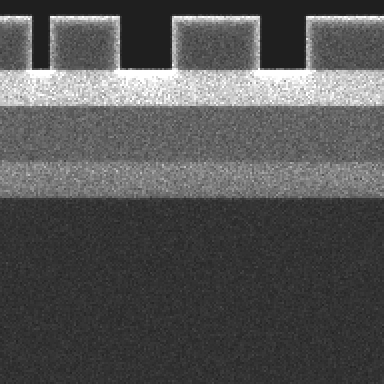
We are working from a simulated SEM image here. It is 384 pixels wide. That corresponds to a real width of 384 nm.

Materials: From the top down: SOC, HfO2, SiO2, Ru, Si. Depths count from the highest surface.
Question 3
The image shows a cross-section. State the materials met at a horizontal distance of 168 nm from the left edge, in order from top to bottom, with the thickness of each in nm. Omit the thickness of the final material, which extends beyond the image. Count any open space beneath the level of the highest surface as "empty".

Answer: empty 54, HfO2 36, SiO2 56, Ru 36, Si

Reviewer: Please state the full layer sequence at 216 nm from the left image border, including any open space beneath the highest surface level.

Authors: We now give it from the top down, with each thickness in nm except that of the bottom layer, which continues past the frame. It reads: SOC 54, HfO2 36, SiO2 56, Ru 36, Si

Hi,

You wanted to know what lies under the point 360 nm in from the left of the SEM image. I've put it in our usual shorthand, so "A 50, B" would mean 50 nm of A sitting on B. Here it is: SOC 54, HfO2 36, SiO2 56, Ru 36, Si